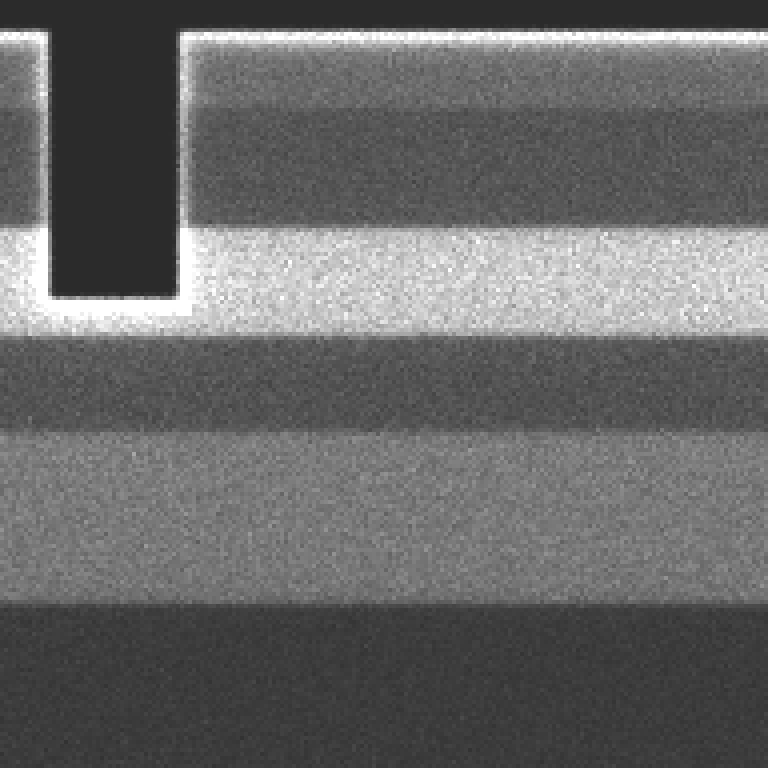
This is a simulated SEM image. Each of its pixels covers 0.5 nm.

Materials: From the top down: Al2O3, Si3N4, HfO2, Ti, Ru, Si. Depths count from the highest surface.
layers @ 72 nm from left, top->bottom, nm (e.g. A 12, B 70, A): empty 134, HfO2 18, Ti 48, Ru 86, Si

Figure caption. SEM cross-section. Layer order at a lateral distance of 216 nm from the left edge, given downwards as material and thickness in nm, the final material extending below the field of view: Al2O3 38, Si3N4 60, HfO2 54, Ti 48, Ru 86, Si